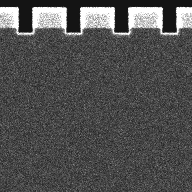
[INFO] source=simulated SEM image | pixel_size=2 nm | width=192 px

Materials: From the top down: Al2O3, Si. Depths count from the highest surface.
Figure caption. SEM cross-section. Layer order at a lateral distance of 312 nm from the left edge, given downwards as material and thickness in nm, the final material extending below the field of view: Al2O3 40, Si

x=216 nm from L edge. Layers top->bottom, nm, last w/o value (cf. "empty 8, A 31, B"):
Al2O3 40, Si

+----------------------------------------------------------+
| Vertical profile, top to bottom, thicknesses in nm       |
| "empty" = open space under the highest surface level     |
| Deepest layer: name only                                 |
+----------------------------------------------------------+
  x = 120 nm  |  Al2O3 40, Si